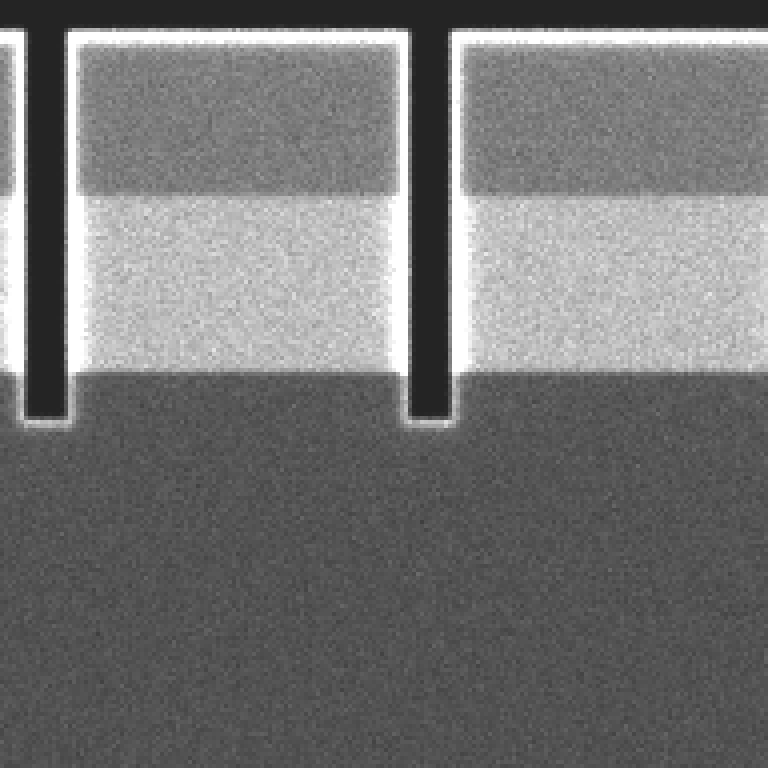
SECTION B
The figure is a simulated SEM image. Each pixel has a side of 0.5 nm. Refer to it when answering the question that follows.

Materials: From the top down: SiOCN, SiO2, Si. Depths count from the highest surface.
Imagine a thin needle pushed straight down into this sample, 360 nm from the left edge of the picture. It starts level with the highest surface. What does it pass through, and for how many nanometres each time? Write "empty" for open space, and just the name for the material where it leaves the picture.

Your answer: SiOCN 82, SiO2 88, Si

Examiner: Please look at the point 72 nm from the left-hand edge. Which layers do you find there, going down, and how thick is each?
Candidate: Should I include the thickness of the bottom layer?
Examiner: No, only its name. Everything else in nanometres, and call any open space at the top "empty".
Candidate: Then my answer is SiOCN 82, SiO2 88, Si